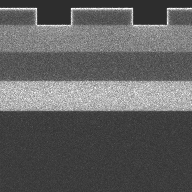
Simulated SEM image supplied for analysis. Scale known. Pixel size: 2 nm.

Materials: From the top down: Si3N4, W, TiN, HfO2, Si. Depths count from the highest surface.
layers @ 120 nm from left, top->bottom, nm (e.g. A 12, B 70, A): empty 34, W 54, TiN 58, HfO2 60, Si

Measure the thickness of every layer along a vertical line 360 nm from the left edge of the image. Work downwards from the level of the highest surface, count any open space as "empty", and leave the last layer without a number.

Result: Si3N4 34, W 54, TiN 58, HfO2 60, Si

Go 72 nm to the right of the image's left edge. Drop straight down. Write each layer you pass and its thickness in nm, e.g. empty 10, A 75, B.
Si3N4 34, W 54, TiN 58, HfO2 60, Si